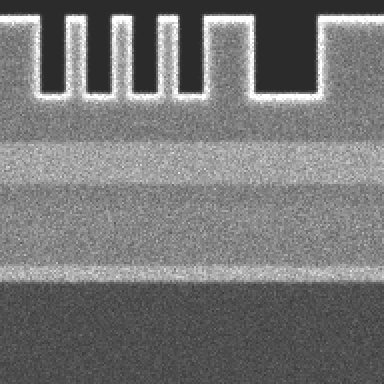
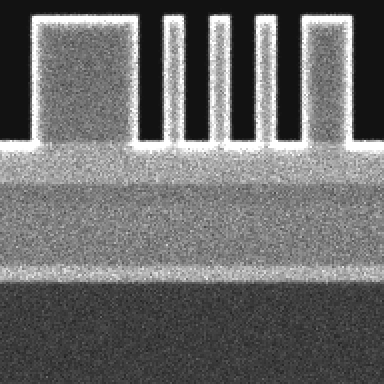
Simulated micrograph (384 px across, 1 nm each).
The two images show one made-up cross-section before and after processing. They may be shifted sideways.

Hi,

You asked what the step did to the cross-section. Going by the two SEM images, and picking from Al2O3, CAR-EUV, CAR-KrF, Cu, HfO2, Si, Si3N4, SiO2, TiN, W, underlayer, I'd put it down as underlayer, removed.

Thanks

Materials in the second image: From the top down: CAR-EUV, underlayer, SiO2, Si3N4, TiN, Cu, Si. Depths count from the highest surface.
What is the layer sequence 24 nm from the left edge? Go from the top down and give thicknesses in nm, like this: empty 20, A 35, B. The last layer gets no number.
empty 126, SiO2 42, Si3N4 20, TiN 62, Cu 16, Si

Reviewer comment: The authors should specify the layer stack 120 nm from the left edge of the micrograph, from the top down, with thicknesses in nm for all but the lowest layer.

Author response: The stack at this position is CAR-EUV 78, underlayer 48, SiO2 42, Si3N4 20, TiN 62, Cu 16, Si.